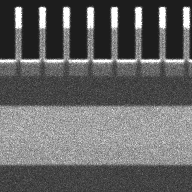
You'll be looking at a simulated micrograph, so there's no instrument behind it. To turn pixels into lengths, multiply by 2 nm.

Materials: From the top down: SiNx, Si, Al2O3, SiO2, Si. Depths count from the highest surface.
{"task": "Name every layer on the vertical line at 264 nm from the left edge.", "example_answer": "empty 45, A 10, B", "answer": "empty 104, SiNx 32, Si 60, Al2O3 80, SiO2 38, Si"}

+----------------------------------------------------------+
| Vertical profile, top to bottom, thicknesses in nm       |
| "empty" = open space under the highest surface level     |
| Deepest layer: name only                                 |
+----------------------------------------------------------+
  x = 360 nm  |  empty 104, SiNx 32, Si 60, Al2O3 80, SiO2 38, Si